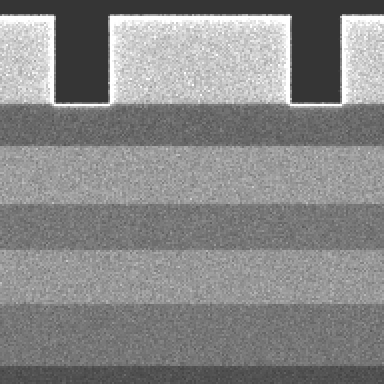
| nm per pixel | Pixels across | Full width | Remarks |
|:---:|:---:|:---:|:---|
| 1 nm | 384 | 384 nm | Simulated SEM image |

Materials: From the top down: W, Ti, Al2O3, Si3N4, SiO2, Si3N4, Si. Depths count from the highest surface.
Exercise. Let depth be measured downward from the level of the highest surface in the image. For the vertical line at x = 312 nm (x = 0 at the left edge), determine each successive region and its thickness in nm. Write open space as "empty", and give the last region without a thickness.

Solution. empty 88, Ti 42, Al2O3 58, Si3N4 46, SiO2 54, Si3N4 62, Si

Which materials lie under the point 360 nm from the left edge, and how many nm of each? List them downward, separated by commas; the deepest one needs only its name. W 88, Ti 42, Al2O3 58, Si3N4 46, SiO2 54, Si3N4 62, Si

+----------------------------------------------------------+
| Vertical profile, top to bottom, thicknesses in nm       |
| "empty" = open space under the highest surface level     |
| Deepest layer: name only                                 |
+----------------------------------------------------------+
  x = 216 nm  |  W 88, Ti 42, Al2O3 58, Si3N4 46, SiO2 54, Si3N4 62, Si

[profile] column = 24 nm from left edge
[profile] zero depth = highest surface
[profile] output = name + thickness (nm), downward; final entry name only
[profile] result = W 88, Ti 42, Al2O3 58, Si3N4 46, SiO2 54, Si3N4 62, Si